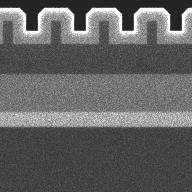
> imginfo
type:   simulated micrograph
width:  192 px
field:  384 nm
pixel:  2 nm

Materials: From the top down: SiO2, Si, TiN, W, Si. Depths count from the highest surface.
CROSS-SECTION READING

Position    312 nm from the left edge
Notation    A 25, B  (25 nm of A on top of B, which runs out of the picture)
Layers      SiO2 26, Si 106, TiN 76, W 30, Si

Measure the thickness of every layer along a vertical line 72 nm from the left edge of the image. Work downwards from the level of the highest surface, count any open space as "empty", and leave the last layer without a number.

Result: empty 46, SiO2 26, Si 60, TiN 76, W 30, Si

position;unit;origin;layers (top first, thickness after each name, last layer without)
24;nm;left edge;SiO2 26, Si 106, TiN 76, W 30, Si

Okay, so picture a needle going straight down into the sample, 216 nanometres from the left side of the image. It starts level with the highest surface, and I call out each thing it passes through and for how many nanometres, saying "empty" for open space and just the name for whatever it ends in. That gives SiO2 26, Si 106, TiN 76, W 30, Si